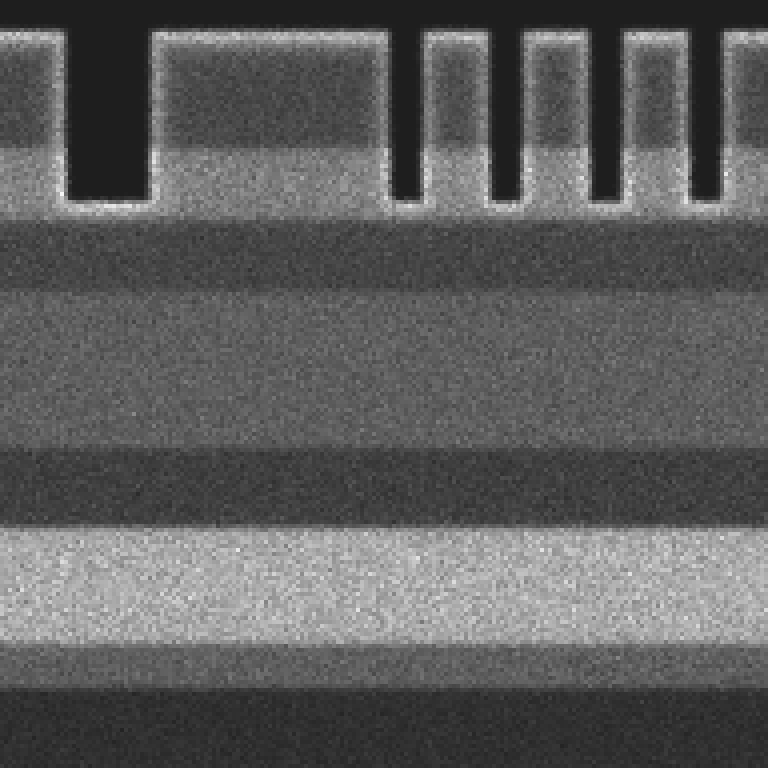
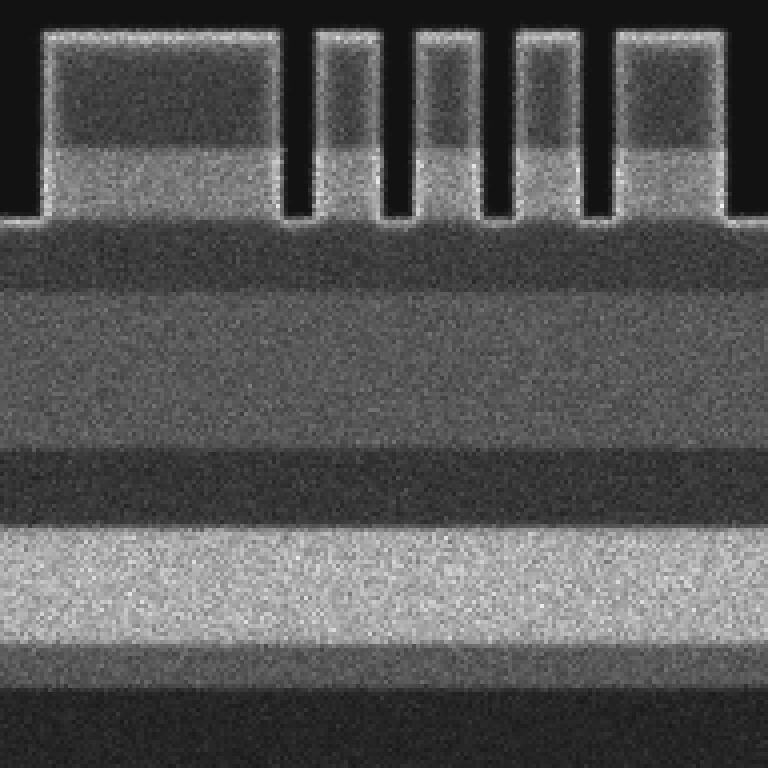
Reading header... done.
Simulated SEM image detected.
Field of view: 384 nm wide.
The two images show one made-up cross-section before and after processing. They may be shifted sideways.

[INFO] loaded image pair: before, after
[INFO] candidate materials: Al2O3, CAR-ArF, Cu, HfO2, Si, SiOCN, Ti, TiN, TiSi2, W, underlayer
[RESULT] removed W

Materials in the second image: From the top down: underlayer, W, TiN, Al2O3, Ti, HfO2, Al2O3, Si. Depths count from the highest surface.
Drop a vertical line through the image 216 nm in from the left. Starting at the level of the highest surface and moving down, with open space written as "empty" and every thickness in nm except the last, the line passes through underlayer 58, W 36, TiN 36, Al2O3 78, Ti 40, HfO2 58, Al2O3 22, Si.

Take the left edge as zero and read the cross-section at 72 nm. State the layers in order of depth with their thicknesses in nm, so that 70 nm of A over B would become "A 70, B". underlayer 58, W 36, TiN 36, Al2O3 78, Ti 40, HfO2 58, Al2O3 22, Si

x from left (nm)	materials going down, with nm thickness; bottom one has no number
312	underlayer 58, W 36, TiN 36, Al2O3 78, Ti 40, HfO2 58, Al2O3 22, Si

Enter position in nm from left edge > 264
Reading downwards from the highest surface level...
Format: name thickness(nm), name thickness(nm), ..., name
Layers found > underlayer 58, W 36, TiN 36, Al2O3 78, Ti 40, HfO2 58, Al2O3 22, Si